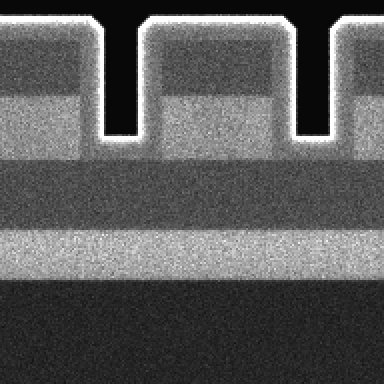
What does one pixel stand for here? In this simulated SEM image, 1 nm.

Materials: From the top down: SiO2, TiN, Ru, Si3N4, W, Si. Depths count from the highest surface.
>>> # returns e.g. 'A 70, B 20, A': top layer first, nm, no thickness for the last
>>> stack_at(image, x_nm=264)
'SiO2 24, TiN 56, Ru 64, Si3N4 70, W 50, Si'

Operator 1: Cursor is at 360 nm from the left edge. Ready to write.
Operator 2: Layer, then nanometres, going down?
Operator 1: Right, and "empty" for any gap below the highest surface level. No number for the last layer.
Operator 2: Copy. SiO2 24, TiN 56, Ru 64, Si3N4 70, W 50, Si